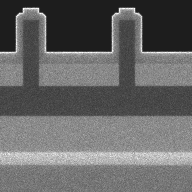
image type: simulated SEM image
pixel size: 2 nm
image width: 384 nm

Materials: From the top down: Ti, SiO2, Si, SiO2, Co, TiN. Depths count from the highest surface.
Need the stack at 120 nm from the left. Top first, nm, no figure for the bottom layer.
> empty 88, Ti 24, SiO2 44, Si 60, SiO2 72, Co 26, TiN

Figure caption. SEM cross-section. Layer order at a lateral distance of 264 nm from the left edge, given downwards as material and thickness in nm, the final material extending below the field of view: Ti 24, Si 192, SiO2 72, Co 26, TiN